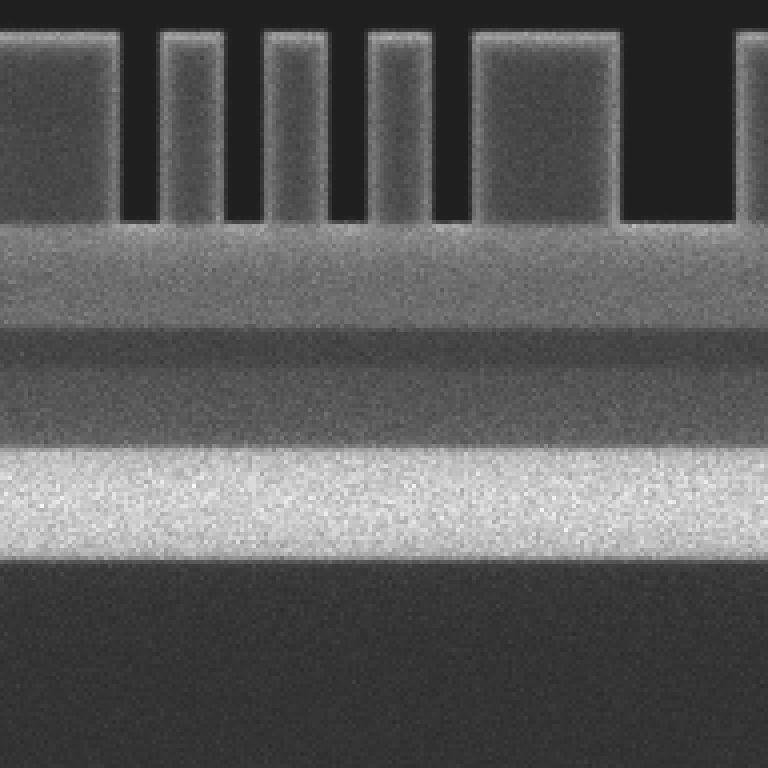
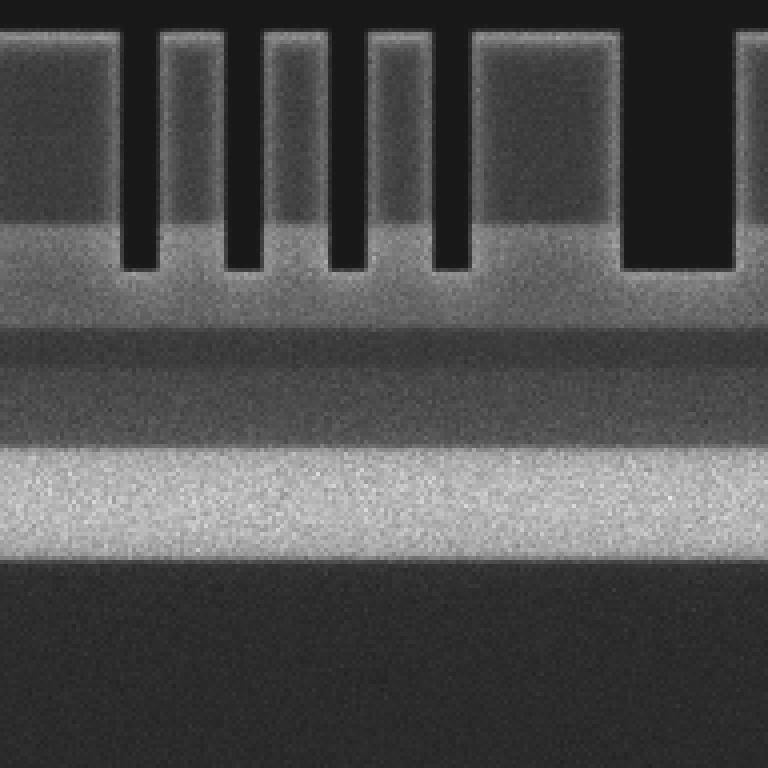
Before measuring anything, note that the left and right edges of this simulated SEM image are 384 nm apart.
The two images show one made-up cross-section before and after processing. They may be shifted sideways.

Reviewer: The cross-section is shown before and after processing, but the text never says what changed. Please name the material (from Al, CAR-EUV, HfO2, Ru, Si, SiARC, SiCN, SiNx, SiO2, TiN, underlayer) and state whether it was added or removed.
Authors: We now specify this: Ru, removed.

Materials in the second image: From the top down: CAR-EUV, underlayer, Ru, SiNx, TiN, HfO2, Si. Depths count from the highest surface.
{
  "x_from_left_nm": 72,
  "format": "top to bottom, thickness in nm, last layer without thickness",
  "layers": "empty 120, Ru 28, SiNx 20, TiN 40, HfO2 56, Si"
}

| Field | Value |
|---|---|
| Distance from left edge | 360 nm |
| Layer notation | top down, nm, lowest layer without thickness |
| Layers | empty 120, Ru 28, SiNx 20, TiN 40, HfO2 56, Si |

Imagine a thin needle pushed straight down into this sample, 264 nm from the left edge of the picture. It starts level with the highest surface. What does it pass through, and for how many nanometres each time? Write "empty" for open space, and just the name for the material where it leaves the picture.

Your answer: CAR-EUV 50, underlayer 46, Ru 52, SiNx 20, TiN 40, HfO2 56, Si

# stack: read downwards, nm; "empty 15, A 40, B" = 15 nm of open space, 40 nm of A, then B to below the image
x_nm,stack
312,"empty 120, Ru 28, SiNx 20, TiN 40, HfO2 56, Si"